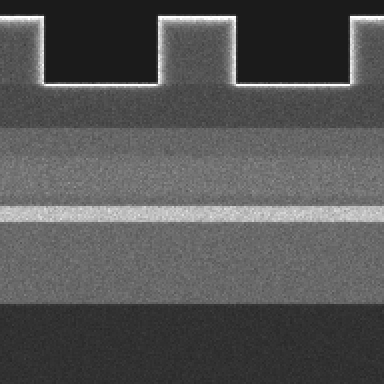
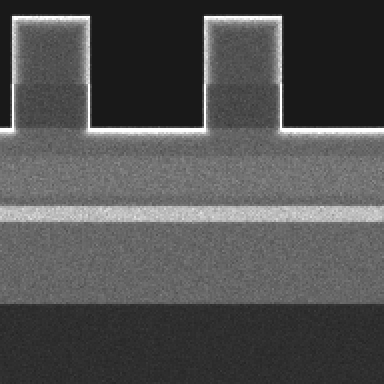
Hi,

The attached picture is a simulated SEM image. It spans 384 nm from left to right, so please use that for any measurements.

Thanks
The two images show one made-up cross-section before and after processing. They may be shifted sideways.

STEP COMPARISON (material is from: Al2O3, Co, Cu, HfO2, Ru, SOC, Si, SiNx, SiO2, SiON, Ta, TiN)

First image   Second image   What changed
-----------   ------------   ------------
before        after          TiN, removed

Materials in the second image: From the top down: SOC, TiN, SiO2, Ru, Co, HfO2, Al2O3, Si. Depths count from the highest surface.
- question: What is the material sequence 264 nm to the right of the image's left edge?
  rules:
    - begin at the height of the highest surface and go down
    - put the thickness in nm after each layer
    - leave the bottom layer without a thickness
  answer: SOC 68, TiN 44, SiO2 28, Ru 40, Co 10, HfO2 16, Al2O3 82, Si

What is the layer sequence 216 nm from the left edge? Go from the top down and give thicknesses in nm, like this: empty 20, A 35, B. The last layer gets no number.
SOC 68, TiN 44, SiO2 28, Ru 40, Co 10, HfO2 16, Al2O3 82, Si